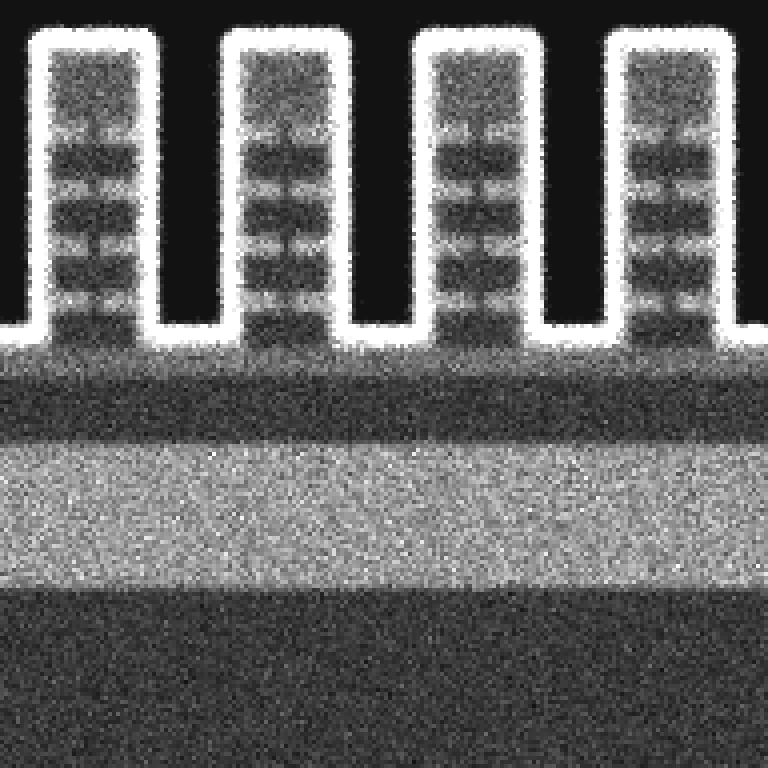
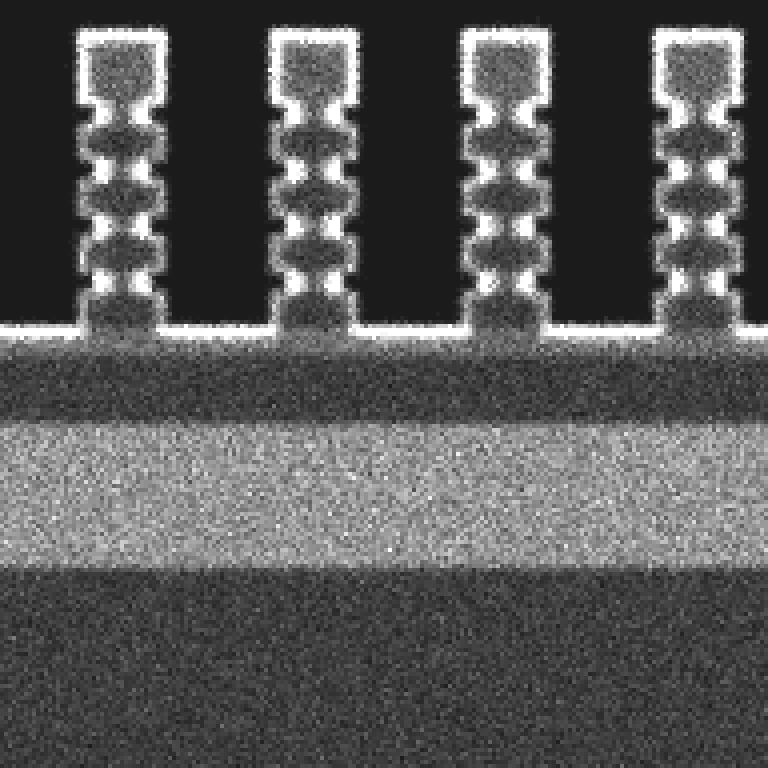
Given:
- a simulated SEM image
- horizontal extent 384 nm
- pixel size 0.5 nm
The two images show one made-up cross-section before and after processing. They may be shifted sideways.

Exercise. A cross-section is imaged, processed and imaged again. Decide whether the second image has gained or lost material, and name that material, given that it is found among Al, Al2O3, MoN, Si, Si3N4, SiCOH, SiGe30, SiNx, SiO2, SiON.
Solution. removed: Al2O3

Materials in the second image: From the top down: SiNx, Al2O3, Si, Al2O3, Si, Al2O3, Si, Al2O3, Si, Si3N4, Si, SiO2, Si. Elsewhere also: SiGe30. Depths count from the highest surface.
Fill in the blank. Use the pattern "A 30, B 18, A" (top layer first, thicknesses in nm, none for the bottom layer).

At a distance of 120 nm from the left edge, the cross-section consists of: empty 148, Si3N4 14, Si 34, SiO2 72, Si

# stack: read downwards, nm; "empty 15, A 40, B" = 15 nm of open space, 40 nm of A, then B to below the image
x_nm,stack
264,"SiNx 36, Al2O3 10, Si 18, Al2O3 10, Si 18, Al2O3 10, Si 18, Al2O3 10, Si 18, Si3N4 14, Si 34, SiO2 72, Si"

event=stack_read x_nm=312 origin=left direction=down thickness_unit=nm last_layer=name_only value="empty 148, Si3N4 14, Si 34, SiO2 72, Si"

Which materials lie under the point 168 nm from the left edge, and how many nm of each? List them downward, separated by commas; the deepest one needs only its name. SiNx 36, Al2O3 10, Si 18, Al2O3 10, Si 18, Al2O3 10, Si 18, Al2O3 10, Si 18, Si3N4 14, Si 34, SiO2 72, Si